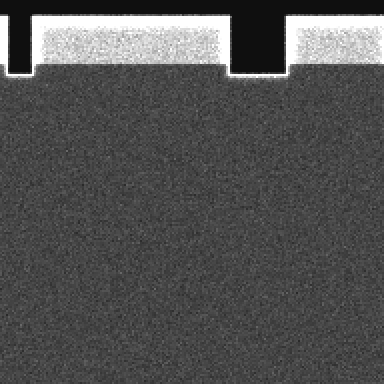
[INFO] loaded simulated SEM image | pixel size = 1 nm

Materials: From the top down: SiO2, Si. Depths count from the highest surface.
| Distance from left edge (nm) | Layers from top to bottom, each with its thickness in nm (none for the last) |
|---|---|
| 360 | SiO2 48, Si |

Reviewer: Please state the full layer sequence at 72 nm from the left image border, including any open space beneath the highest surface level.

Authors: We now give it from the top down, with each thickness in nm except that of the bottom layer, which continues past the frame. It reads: SiO2 48, Si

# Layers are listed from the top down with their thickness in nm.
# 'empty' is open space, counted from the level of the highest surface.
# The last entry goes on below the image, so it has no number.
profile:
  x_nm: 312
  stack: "SiO2 48, Si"